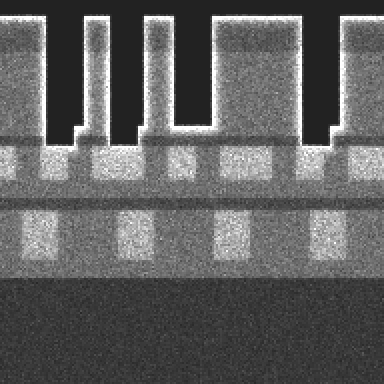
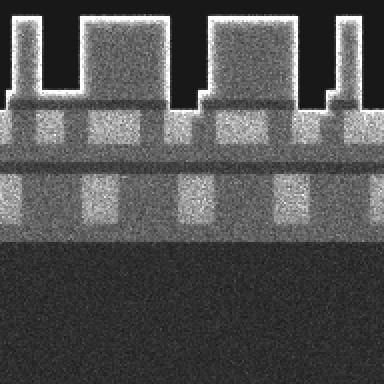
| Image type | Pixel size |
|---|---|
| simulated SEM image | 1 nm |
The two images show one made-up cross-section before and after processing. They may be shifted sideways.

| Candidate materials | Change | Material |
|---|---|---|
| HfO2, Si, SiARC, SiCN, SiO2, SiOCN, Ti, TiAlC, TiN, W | removed | SiARC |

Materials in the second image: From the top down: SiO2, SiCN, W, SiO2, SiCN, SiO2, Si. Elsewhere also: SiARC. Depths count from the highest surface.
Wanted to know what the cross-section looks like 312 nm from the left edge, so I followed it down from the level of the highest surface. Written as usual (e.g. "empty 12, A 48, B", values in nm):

empty 94, W 34, SiO2 18, SiCN 12, SiO2 68, Si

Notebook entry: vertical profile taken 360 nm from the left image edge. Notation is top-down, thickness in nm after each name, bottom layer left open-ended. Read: SiO2 84, SiCN 10, W 34, SiO2 18, SiCN 12, SiO2 68, Si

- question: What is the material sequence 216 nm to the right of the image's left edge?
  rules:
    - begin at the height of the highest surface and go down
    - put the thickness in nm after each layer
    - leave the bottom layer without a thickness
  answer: SiO2 84, SiCN 10, W 34, SiO2 18, SiCN 12, SiO2 68, Si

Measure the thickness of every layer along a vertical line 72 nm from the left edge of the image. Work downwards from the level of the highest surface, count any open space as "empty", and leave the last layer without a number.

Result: empty 74, SiO2 10, SiCN 10, SiO2 52, SiCN 12, SiO2 68, Si